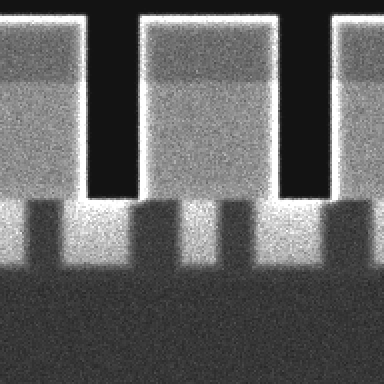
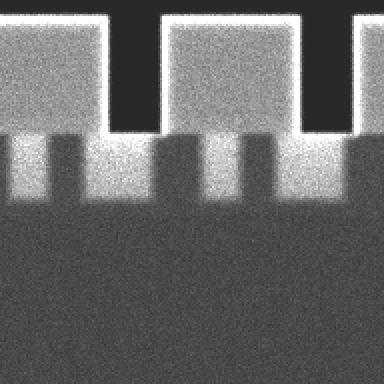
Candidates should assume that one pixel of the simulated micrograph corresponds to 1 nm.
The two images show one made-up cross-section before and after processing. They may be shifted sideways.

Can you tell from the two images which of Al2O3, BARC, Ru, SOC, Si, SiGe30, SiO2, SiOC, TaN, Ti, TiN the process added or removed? Yes, it removed SOC.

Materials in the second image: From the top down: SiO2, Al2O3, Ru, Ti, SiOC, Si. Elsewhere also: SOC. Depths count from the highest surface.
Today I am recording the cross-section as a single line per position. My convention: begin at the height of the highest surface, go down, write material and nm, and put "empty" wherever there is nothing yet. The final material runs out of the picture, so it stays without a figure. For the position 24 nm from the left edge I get SiO2 102, Al2O3 16, Ru 64, Ti 6, SiOC 12, Si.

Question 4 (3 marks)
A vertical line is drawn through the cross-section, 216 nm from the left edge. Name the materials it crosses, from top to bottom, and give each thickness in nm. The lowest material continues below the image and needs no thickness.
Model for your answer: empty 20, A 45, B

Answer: SiO2 102, Al2O3 16, Ru 64, Ti 6, SiOC 12, Si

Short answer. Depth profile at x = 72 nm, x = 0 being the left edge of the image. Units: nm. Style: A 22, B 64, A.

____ SiO2 102, Al2O3 16, SiOC 82, Si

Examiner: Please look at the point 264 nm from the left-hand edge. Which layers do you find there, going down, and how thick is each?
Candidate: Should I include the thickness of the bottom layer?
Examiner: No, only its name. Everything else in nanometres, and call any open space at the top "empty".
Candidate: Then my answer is SiO2 102, Al2O3 16, SiOC 82, Si